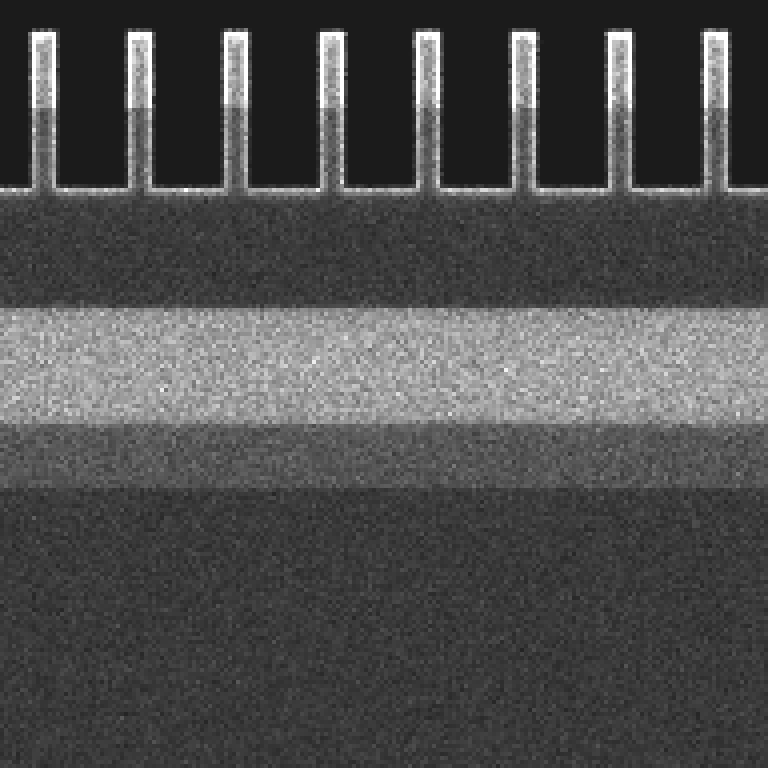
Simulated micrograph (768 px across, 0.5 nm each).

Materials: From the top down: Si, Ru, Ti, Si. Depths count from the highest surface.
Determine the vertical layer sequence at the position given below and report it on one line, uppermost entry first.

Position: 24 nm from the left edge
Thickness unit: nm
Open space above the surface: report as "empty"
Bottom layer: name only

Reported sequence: Si 138, Ru 58, Ti 32, Si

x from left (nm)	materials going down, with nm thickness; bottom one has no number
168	Si 138, Ru 58, Ti 32, Si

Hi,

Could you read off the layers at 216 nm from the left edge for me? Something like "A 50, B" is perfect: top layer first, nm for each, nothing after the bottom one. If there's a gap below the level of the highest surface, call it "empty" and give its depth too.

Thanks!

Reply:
Si 138, Ru 58, Ti 32, Si